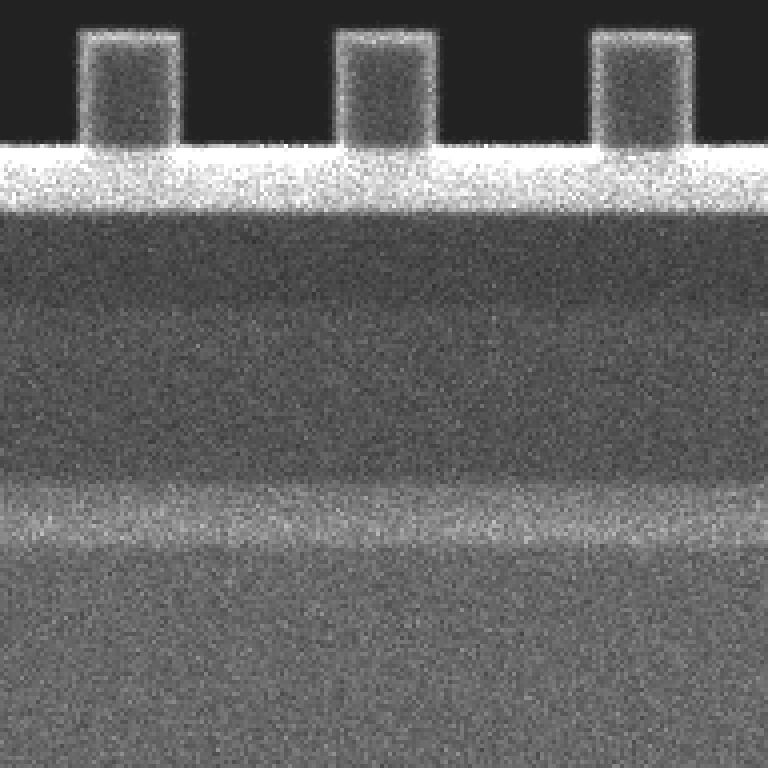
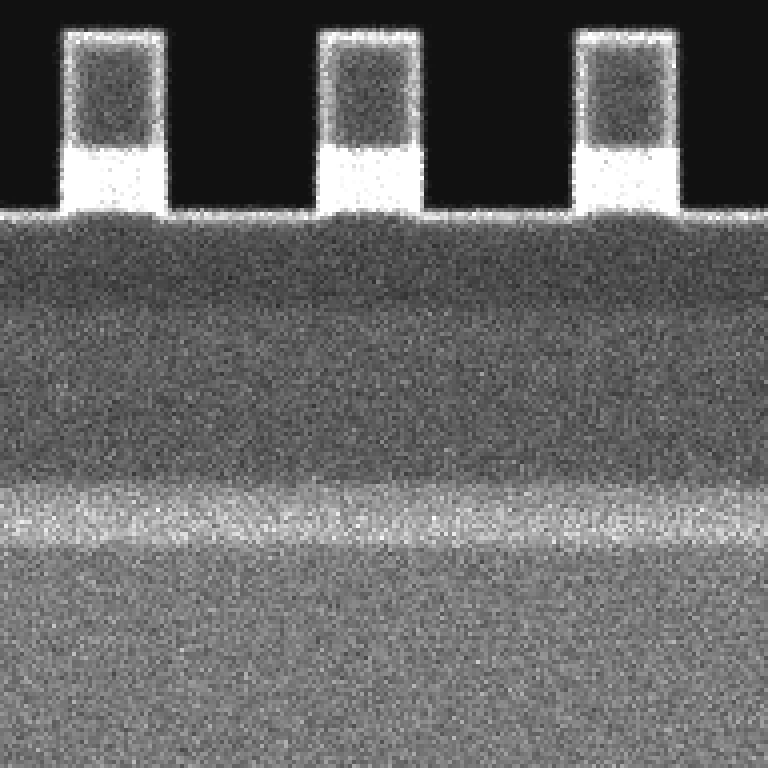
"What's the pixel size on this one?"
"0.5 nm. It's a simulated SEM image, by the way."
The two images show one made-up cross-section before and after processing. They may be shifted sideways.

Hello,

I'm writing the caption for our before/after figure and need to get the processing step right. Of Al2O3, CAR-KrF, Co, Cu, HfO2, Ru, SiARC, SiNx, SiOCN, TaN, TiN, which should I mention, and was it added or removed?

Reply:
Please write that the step removed HfO2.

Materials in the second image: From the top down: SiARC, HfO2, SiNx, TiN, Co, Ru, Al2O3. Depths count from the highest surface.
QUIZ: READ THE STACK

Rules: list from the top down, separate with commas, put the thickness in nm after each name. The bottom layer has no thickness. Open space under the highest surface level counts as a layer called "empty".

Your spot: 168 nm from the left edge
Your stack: SiARC 58, HfO2 32, SiNx 48, TiN 88, Co 14, Ru 16, Al2O3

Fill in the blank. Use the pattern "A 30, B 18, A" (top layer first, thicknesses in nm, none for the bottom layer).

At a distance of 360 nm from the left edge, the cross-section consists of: empty 90, SiNx 48, TiN 88, Co 14, Ru 16, Al2O3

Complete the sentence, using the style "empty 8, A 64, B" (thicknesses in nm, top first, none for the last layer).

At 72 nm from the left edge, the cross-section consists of SiARC 58, HfO2 32, SiNx 48, TiN 88, Co 14, Ru 16, Al2O3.